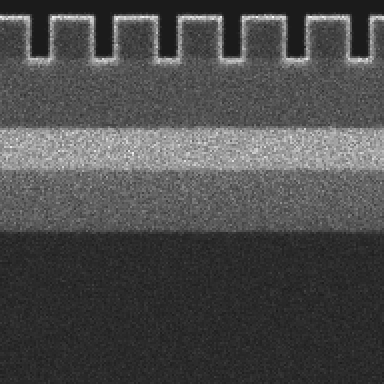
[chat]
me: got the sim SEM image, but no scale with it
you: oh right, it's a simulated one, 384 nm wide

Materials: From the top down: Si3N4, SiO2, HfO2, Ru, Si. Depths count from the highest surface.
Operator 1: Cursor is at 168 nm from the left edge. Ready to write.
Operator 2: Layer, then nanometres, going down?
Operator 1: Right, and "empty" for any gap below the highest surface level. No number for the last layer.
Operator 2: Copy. empty 42, SiO2 70, HfO2 42, Ru 62, Si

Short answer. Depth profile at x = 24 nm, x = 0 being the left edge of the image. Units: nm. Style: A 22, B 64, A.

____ Si3N4 42, SiO2 70, HfO2 42, Ru 62, Si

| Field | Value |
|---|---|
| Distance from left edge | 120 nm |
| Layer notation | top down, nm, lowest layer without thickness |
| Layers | Si3N4 42, SiO2 70, HfO2 42, Ru 62, Si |